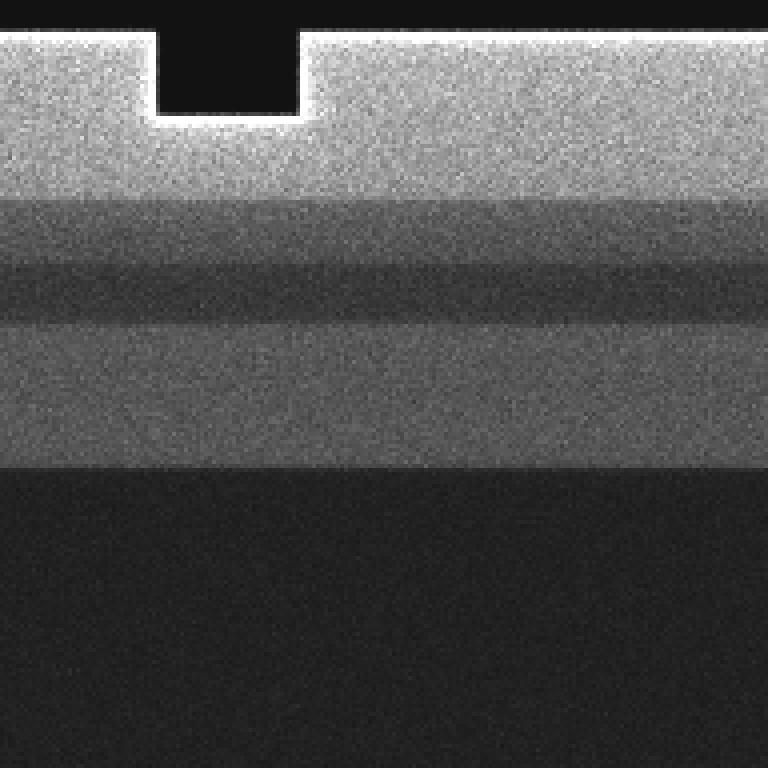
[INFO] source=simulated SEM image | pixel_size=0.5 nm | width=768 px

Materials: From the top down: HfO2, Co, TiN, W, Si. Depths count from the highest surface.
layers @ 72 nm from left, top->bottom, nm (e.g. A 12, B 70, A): HfO2 84, Co 32, TiN 30, W 72, Si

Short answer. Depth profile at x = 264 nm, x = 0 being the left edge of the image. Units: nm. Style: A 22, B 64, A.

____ HfO2 84, Co 32, TiN 30, W 72, Si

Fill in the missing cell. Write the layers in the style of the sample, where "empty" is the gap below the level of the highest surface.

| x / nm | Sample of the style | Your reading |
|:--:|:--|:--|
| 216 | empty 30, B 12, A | HfO2 84, Co 32, TiN 30, W 72, Si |